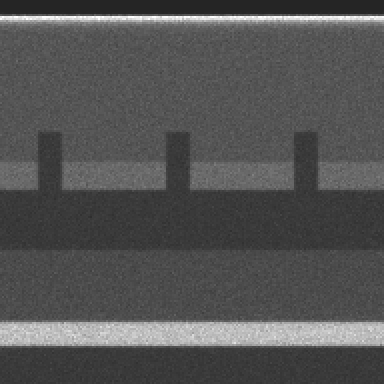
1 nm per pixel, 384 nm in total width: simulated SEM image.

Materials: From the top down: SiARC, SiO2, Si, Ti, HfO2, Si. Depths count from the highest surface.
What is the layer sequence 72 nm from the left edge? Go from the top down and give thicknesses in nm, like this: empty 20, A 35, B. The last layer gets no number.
SiARC 146, SiO2 28, Si 60, Ti 72, HfO2 24, Si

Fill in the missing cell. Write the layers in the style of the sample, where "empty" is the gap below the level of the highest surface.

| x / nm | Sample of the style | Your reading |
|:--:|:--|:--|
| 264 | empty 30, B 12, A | SiARC 146, SiO2 28, Si 60, Ti 72, HfO2 24, Si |